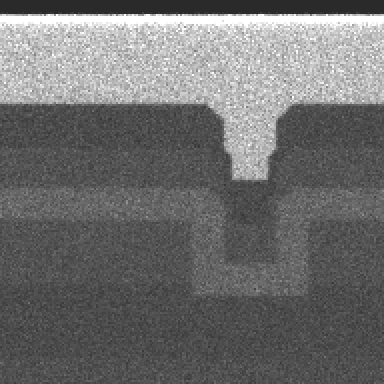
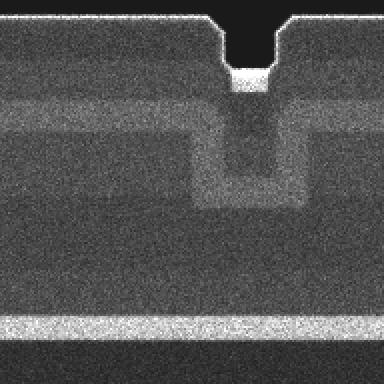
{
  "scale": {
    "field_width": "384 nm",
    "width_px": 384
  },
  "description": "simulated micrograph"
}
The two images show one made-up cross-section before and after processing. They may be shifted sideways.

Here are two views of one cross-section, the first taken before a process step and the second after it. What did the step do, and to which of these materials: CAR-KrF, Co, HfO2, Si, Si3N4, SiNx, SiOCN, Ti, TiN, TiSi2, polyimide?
It removed HfO2.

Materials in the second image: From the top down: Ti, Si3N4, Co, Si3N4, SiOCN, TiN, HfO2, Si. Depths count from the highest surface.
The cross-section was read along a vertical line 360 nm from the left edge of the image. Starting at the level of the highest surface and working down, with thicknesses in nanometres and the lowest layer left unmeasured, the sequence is Ti 44, Si3N4 40, Co 32, Si3N4 64, SiOCN 74, TiN 46, HfO2 24, Si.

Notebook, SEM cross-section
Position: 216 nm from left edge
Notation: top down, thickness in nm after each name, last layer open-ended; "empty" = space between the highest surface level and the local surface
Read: empty 10, Ti 44, Si3N4 40, Co 98, SiOCN 62, TiN 46, HfO2 24, Si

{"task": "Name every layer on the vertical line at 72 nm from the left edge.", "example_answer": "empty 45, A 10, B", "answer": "Ti 44, Si3N4 40, Co 32, Si3N4 64, SiOCN 74, TiN 46, HfO2 24, Si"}